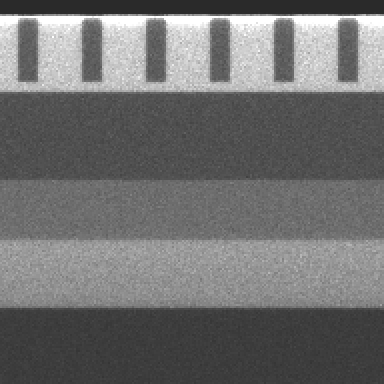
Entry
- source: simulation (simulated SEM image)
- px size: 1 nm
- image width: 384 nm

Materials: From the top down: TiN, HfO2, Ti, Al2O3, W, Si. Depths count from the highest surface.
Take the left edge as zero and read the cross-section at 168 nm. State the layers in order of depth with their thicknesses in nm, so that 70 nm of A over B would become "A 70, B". HfO2 76, Ti 88, Al2O3 60, W 68, Si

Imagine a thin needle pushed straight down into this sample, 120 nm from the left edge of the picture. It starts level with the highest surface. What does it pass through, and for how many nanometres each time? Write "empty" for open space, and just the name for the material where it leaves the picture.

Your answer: HfO2 76, Ti 88, Al2O3 60, W 68, Si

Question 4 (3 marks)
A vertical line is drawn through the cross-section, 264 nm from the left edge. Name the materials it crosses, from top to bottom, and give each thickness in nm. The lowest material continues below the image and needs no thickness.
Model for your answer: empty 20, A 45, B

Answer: HfO2 76, Ti 88, Al2O3 60, W 68, Si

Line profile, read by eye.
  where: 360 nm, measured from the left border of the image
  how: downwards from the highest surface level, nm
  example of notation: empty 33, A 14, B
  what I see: HfO2 76, Ti 88, Al2O3 60, W 68, Si